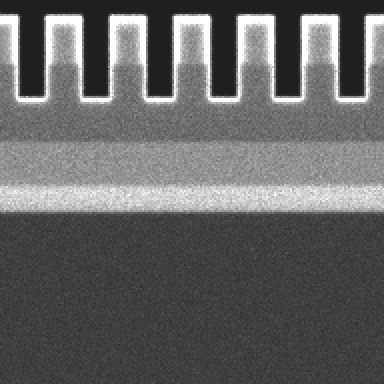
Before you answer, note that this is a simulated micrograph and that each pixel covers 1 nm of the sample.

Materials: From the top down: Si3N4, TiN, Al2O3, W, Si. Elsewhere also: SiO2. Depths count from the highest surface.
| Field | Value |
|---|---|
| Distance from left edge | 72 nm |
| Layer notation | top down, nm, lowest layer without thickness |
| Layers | SiO2 48, TiN 78, Al2O3 44, W 26, Si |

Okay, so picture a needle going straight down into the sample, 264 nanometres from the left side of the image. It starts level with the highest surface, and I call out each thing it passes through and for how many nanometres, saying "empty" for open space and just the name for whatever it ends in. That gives SiO2 48, TiN 78, Al2O3 44, W 26, Si